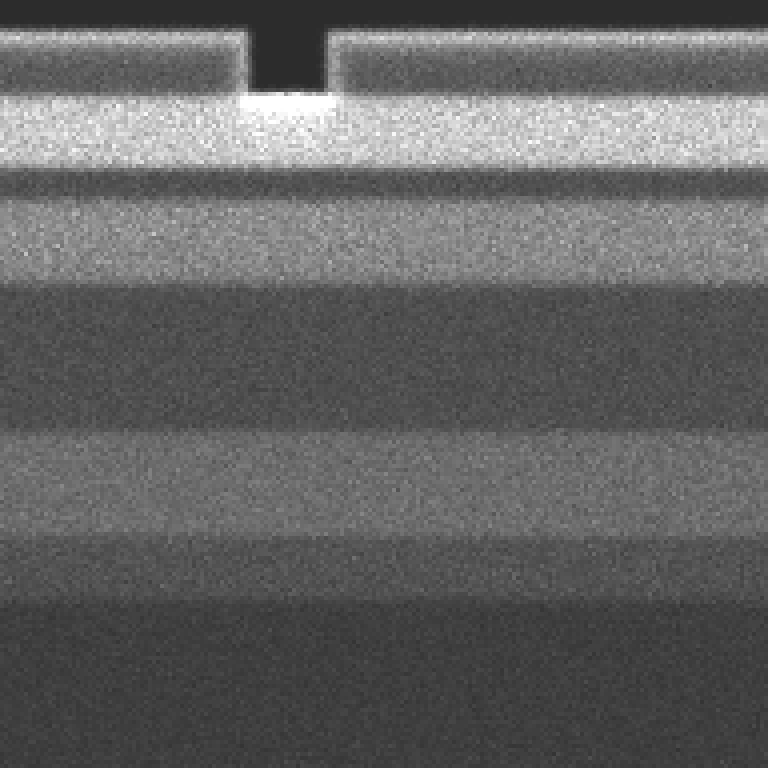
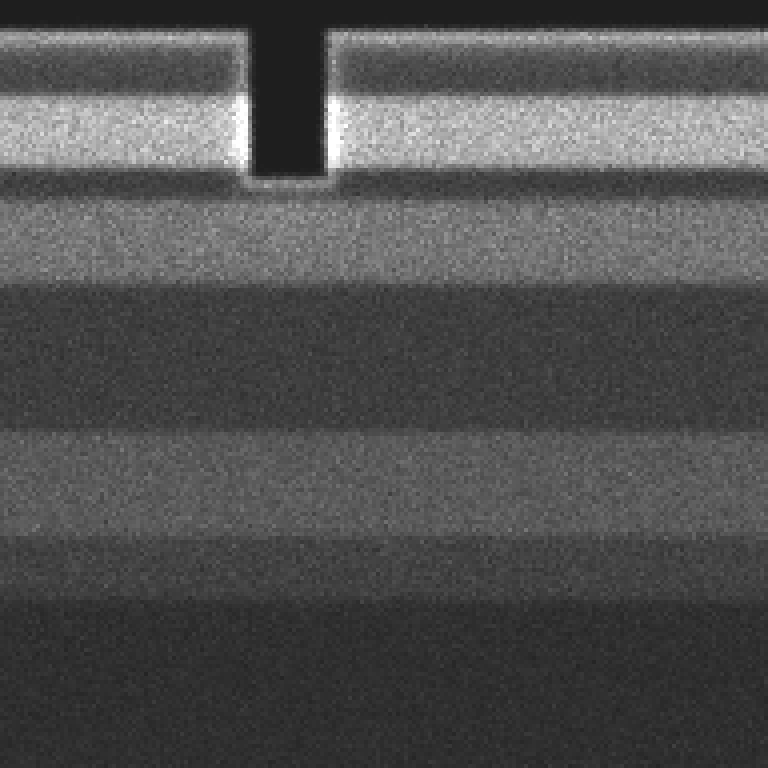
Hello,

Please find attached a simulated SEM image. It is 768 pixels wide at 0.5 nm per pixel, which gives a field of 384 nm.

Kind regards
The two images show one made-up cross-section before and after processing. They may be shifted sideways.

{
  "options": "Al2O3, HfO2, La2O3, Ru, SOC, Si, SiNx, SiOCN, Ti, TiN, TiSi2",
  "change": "removed",
  "material": "HfO2 and SiOCN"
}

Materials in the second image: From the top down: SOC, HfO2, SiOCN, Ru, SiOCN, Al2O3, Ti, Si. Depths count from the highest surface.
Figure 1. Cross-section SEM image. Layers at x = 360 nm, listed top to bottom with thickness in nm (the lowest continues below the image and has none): SOC 32, HfO2 36, SiOCN 16, Ru 42, SiOCN 74, Al2O3 52, Ti 32, Si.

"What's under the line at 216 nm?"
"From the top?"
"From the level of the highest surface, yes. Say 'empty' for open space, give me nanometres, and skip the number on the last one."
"SOC 32, HfO2 36, SiOCN 16, Ru 42, SiOCN 74, Al2O3 52, Ti 32, Si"